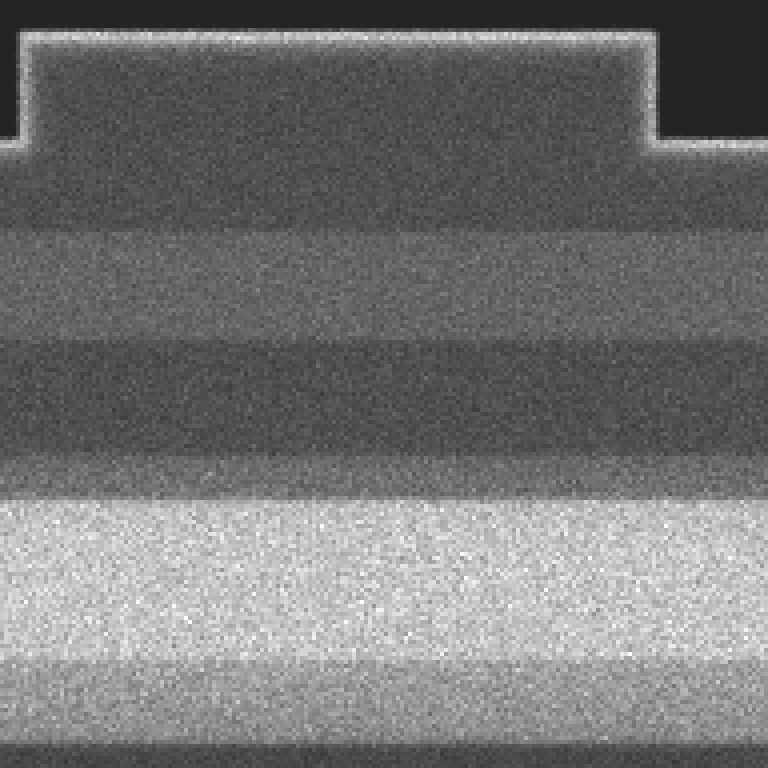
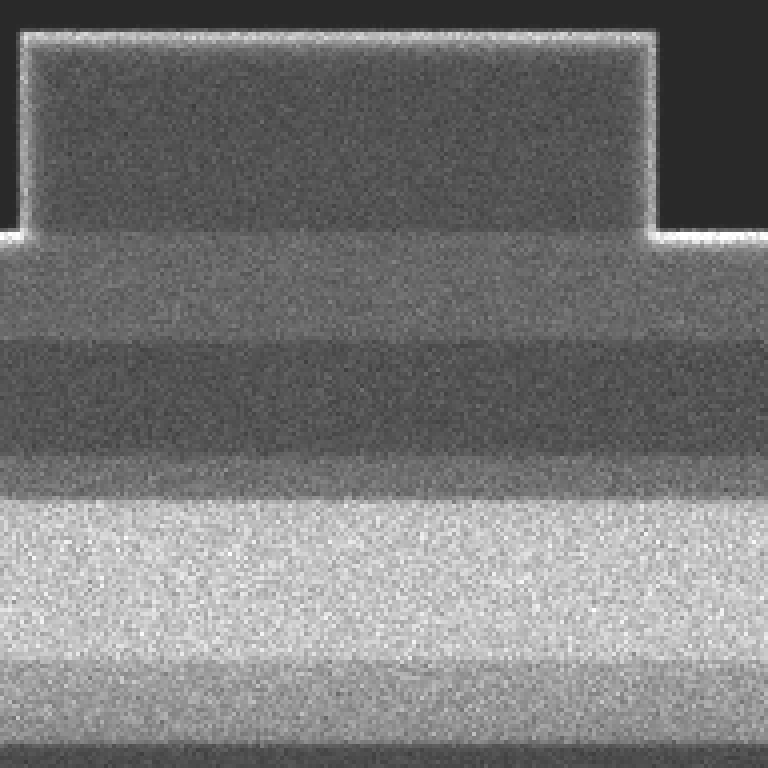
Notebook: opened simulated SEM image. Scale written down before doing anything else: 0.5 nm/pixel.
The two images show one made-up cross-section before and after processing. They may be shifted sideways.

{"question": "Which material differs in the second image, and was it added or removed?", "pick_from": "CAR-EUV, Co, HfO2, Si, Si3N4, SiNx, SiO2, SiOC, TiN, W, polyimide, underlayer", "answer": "underlayer, removed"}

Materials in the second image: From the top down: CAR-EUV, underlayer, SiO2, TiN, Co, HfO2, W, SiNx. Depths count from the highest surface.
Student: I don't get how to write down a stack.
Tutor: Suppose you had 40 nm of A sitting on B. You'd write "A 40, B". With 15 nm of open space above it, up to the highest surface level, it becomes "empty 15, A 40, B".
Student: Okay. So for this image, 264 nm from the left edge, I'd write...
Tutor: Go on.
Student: CAR-EUV 54, underlayer 46, SiO2 54, TiN 58, Co 22, HfO2 80, W 42, SiNx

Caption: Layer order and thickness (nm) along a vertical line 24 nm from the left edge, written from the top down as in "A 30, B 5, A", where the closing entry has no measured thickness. CAR-EUV 54, underlayer 46, SiO2 54, TiN 58, Co 22, HfO2 80, W 42, SiNx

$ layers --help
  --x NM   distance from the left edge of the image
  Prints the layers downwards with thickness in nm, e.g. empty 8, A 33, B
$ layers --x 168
CAR-EUV 54, underlayer 46, SiO2 54, TiN 58, Co 22, HfO2 80, W 42, SiNx